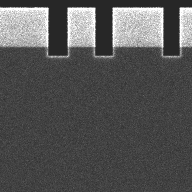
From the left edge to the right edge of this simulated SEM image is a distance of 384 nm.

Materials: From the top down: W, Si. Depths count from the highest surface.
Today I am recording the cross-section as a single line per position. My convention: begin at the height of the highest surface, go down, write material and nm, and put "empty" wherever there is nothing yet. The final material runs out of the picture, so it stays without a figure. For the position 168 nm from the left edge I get W 78, Si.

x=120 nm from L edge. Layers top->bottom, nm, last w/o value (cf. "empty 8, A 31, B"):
empty 96, Si